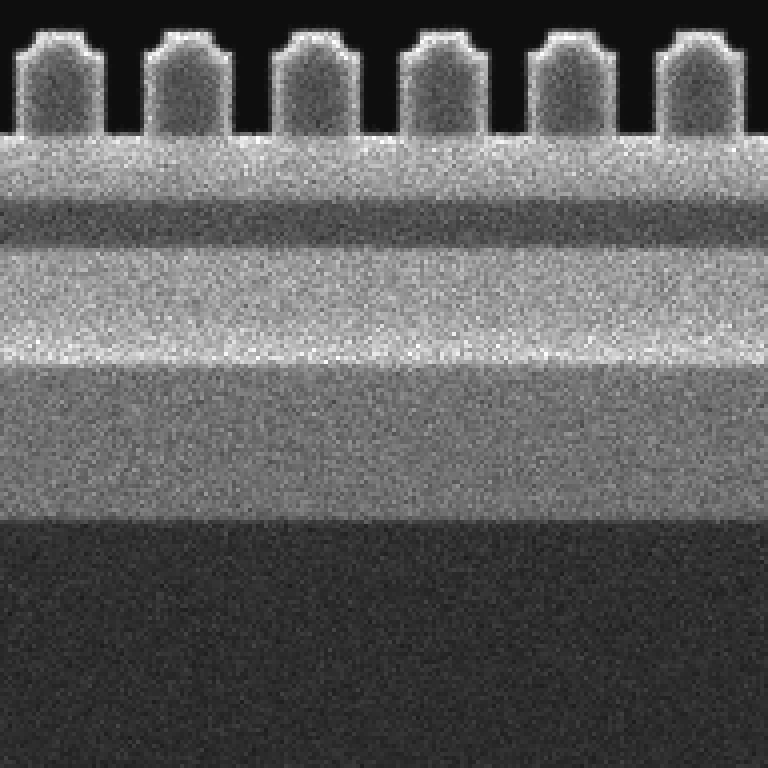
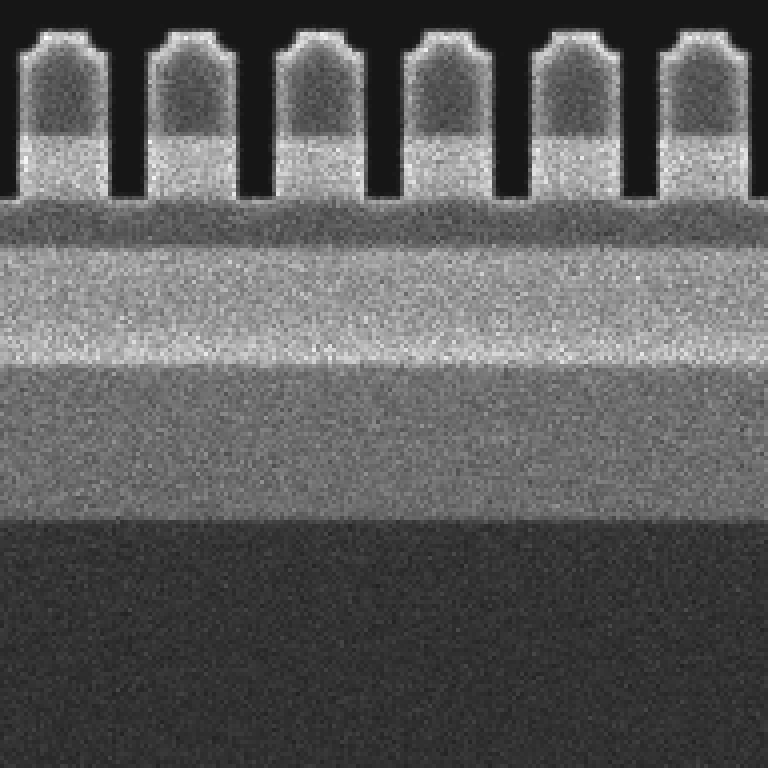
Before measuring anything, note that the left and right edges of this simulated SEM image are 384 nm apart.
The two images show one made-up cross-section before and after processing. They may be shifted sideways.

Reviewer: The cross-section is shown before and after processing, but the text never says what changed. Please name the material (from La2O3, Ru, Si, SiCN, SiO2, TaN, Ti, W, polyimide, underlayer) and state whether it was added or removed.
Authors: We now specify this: Ru, removed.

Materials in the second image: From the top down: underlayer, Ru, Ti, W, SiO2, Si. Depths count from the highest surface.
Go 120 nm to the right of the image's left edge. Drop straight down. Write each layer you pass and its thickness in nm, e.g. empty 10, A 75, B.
empty 84, Ti 24, W 58, SiO2 78, Si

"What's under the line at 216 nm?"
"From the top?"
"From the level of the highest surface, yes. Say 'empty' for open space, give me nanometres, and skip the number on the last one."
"underlayer 52, Ru 32, Ti 24, W 58, SiO2 78, Si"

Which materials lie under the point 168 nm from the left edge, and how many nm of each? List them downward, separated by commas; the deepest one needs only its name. underlayer 52, Ru 32, Ti 24, W 58, SiO2 78, Si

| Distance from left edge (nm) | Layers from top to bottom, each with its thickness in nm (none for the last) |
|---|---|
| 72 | empty 84, Ti 24, W 58, SiO2 78, Si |